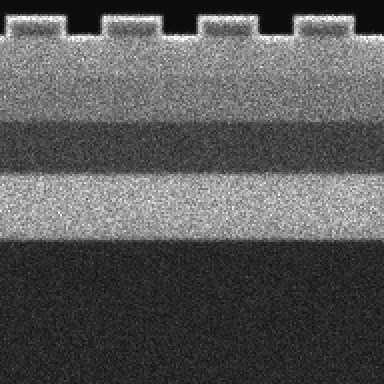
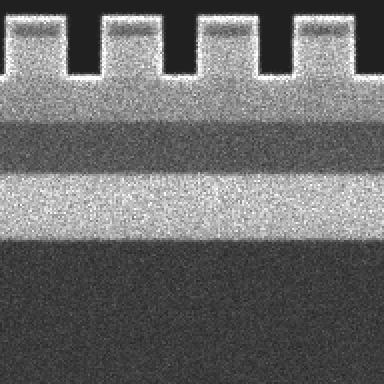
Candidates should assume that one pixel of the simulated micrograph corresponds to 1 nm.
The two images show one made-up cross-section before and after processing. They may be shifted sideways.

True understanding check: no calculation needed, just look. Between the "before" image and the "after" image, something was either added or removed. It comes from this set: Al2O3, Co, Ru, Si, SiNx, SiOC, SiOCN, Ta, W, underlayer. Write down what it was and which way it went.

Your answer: Ru (removed)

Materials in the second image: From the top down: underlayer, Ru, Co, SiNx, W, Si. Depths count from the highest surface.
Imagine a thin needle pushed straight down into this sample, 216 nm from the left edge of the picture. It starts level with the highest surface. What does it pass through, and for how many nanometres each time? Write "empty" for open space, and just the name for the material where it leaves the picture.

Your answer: underlayer 20, Ru 40, Co 46, SiNx 52, W 66, Si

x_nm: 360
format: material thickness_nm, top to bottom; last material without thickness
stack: empty 60, Co 46, SiNx 52, W 66, Si